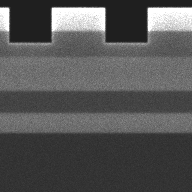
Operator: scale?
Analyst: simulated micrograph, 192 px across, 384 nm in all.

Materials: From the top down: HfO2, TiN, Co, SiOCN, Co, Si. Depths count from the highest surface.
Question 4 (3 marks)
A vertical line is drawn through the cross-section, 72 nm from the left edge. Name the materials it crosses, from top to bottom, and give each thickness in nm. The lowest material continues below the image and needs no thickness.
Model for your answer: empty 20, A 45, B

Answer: empty 70, TiN 28, Co 68, SiOCN 44, Co 40, Si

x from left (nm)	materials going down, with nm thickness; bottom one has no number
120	HfO2 46, TiN 52, Co 68, SiOCN 44, Co 40, Si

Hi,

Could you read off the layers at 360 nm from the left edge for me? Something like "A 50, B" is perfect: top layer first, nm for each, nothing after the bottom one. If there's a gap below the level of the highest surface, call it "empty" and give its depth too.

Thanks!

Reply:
HfO2 46, TiN 52, Co 68, SiOCN 44, Co 40, Si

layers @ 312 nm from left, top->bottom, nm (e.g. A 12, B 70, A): HfO2 46, TiN 52, Co 68, SiOCN 44, Co 40, Si